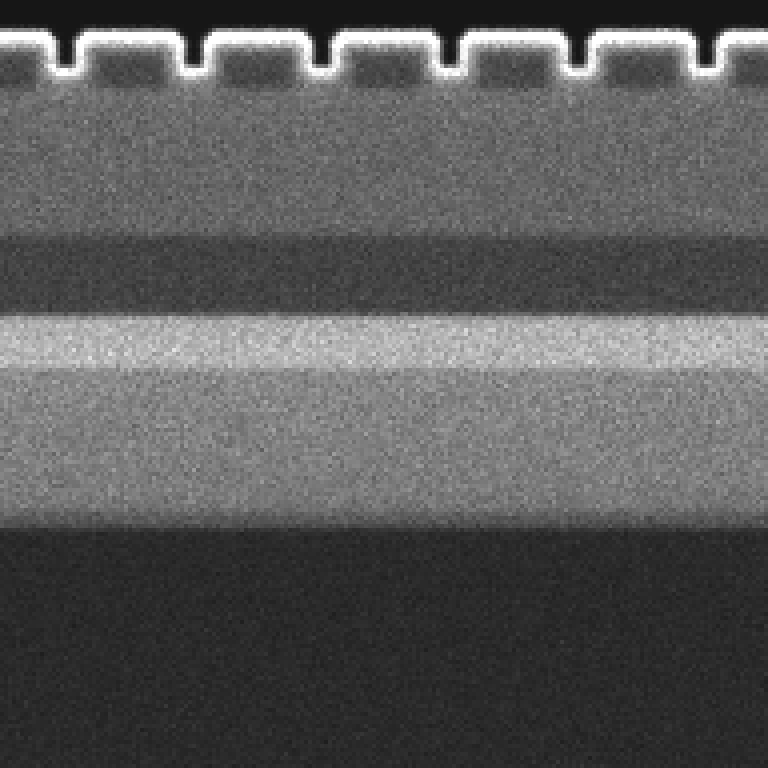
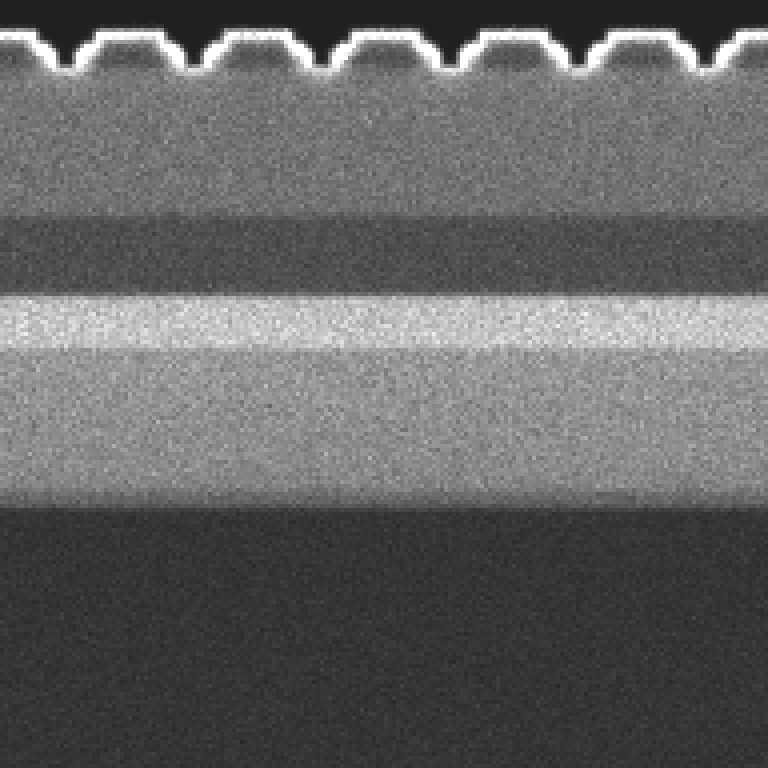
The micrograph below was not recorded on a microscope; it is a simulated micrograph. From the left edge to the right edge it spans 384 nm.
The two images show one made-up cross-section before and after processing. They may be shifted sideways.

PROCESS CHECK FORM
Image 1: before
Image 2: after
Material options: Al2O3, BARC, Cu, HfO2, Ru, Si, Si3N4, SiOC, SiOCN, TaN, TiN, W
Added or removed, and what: removed, Al2O3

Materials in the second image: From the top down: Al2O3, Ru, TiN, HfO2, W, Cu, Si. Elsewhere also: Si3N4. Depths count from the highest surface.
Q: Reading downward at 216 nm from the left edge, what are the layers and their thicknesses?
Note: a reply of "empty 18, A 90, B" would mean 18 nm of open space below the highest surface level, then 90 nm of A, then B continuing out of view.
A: empty 8, Al2O3 10, Ru 74, TiN 40, HfO2 26, W 72, Cu 8, Si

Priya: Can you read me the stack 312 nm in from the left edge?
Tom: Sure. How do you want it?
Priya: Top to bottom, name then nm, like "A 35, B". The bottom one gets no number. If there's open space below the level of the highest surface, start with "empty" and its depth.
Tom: Si3N4 18, Ru 74, TiN 40, HfO2 26, W 72, Cu 8, Si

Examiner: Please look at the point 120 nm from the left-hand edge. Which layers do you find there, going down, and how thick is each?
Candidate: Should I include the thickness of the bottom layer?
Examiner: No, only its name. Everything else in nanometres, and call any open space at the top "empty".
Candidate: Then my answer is Si3N4 18, Ru 74, TiN 40, HfO2 26, W 72, Cu 8, Si